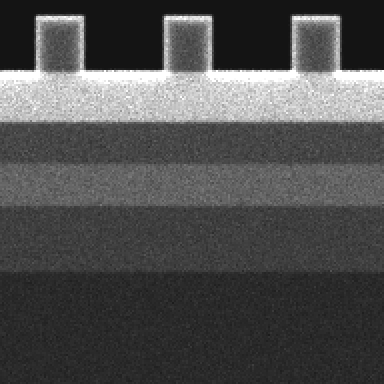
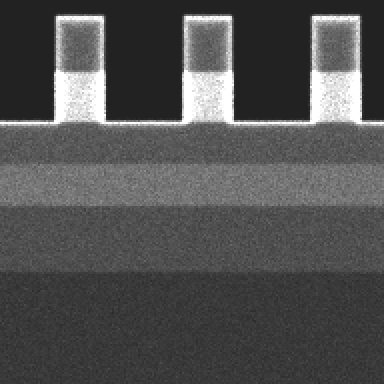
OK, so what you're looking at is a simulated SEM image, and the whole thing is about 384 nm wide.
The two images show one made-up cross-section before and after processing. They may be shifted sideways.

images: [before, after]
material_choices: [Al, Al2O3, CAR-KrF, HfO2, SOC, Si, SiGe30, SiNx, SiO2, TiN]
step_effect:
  removed: HfO2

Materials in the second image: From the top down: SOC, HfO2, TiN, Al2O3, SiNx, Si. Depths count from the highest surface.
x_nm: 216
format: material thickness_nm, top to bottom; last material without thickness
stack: SOC 56, HfO2 50, TiN 42, Al2O3 42, SiNx 66, Si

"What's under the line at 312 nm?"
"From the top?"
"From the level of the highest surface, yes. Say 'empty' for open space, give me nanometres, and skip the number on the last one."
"SOC 56, HfO2 50, TiN 42, Al2O3 42, SiNx 66, Si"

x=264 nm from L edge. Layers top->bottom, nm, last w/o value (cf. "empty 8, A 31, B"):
empty 106, TiN 42, Al2O3 42, SiNx 66, Si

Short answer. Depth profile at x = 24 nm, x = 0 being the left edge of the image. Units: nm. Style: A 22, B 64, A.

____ empty 106, TiN 42, Al2O3 42, SiNx 66, Si